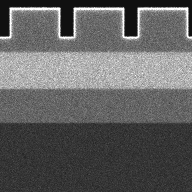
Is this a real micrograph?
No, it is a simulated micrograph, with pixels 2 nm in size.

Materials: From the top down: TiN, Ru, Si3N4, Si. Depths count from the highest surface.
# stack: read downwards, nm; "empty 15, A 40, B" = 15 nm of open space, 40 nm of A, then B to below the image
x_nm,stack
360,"TiN 88, Ru 74, Si3N4 68, Si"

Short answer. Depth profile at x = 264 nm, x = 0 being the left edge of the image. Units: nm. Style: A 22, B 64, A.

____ empty 58, TiN 30, Ru 74, Si3N4 68, Si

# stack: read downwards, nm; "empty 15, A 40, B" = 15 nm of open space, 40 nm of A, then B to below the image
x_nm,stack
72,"TiN 88, Ru 74, Si3N4 68, Si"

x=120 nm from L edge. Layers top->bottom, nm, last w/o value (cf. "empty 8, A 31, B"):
empty 58, TiN 30, Ru 74, Si3N4 68, Si